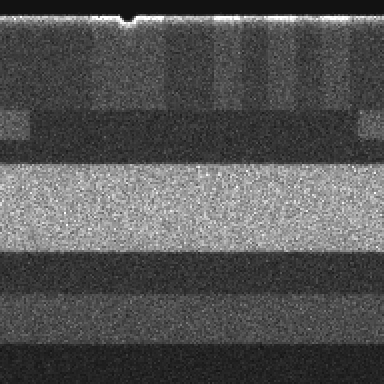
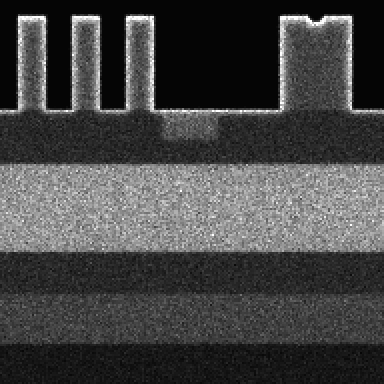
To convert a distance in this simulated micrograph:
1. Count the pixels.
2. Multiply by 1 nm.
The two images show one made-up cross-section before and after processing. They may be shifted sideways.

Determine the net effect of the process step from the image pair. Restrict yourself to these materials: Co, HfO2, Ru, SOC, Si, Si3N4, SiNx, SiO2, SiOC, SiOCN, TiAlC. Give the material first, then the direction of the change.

SOC: removed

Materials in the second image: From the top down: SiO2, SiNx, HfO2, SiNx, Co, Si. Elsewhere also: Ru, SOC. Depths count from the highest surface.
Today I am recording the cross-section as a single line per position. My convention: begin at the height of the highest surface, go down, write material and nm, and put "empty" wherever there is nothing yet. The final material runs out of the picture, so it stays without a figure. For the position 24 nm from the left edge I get SiO2 94, SiNx 54, HfO2 88, SiNx 42, Co 50, Si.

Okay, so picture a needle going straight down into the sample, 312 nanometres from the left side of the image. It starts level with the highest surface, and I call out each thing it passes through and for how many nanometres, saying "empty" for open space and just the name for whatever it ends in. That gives empty 6, SiO2 88, SiNx 54, HfO2 88, SiNx 42, Co 50, Si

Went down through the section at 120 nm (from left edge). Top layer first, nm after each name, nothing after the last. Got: empty 94, SiNx 54, HfO2 88, SiNx 42, Co 50, Si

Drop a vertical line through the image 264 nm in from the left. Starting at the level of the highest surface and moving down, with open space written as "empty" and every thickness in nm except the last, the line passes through empty 94, SiNx 54, HfO2 88, SiNx 42, Co 50, Si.